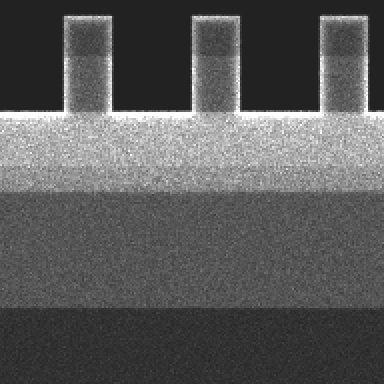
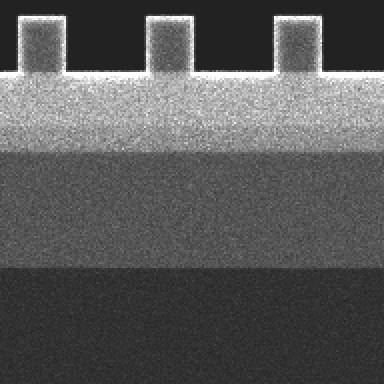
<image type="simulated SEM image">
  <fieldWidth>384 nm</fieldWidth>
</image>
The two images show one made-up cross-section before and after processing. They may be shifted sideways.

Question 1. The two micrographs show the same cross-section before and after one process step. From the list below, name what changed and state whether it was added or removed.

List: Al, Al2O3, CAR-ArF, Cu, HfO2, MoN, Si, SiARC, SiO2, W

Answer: SiARC, removed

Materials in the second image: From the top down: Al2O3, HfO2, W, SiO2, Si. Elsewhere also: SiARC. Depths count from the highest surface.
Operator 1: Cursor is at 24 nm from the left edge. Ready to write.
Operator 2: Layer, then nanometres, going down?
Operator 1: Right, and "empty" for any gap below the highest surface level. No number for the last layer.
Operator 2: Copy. Al2O3 56, HfO2 54, W 26, SiO2 116, Si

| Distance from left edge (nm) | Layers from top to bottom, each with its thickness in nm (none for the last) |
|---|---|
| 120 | empty 56, HfO2 54, W 26, SiO2 116, Si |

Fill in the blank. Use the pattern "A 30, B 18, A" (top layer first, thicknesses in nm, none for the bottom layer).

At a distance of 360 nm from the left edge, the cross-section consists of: empty 56, HfO2 54, W 26, SiO2 116, Si